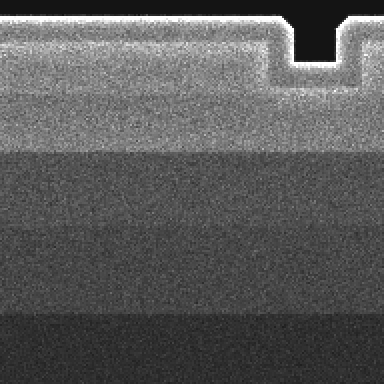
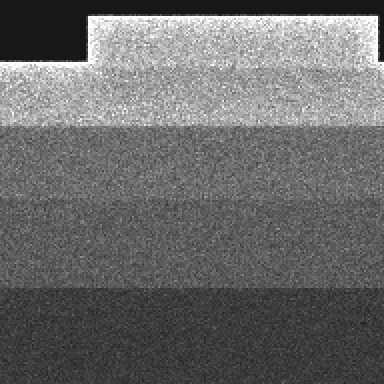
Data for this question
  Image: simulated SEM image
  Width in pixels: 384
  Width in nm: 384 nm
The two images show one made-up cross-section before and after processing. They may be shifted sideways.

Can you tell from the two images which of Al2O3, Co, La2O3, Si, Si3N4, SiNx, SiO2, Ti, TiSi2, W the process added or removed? Yes, it removed Al2O3.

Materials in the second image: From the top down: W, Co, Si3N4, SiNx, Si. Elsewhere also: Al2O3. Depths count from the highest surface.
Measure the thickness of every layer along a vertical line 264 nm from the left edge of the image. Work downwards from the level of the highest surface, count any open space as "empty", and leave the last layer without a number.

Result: W 52, Co 58, Si3N4 74, SiNx 88, Si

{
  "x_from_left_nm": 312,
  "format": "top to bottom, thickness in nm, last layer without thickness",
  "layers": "W 52, Co 58, Si3N4 74, SiNx 88, Si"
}